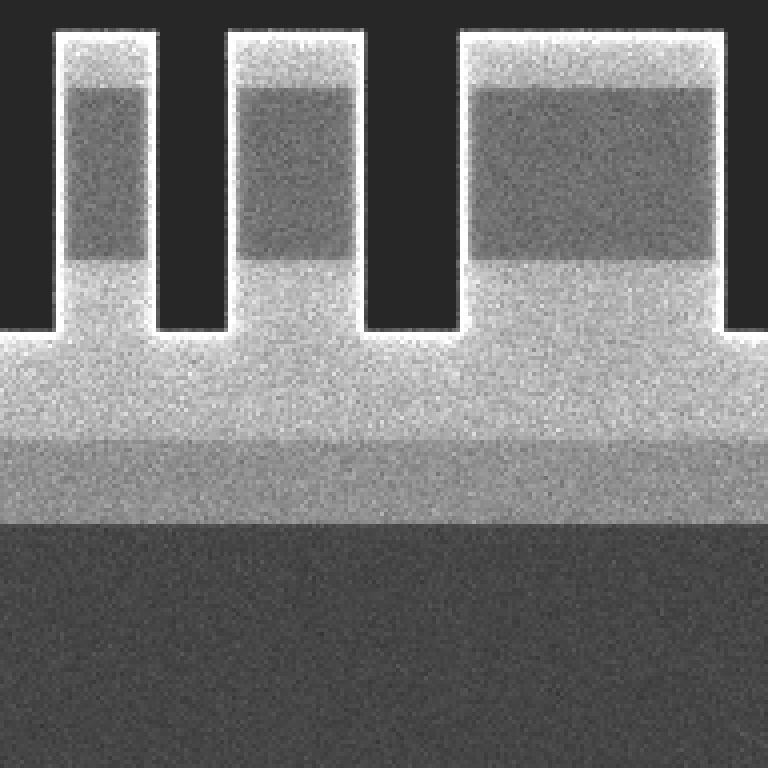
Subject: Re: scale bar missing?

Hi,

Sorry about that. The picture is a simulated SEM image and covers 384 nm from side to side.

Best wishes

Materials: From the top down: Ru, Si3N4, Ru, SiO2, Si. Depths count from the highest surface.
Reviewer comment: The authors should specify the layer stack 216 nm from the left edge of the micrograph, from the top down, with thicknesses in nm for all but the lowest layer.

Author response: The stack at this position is empty 150, Ru 54, SiO2 42, Si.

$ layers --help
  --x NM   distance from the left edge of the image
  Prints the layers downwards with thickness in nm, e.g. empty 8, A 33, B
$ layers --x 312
Ru 28, Si3N4 86, Ru 90, SiO2 42, Si